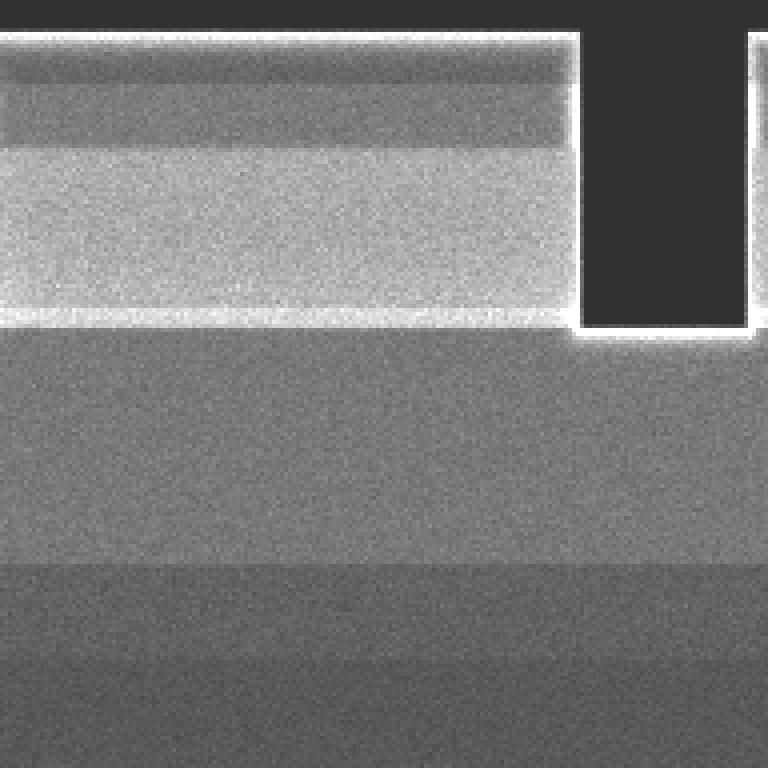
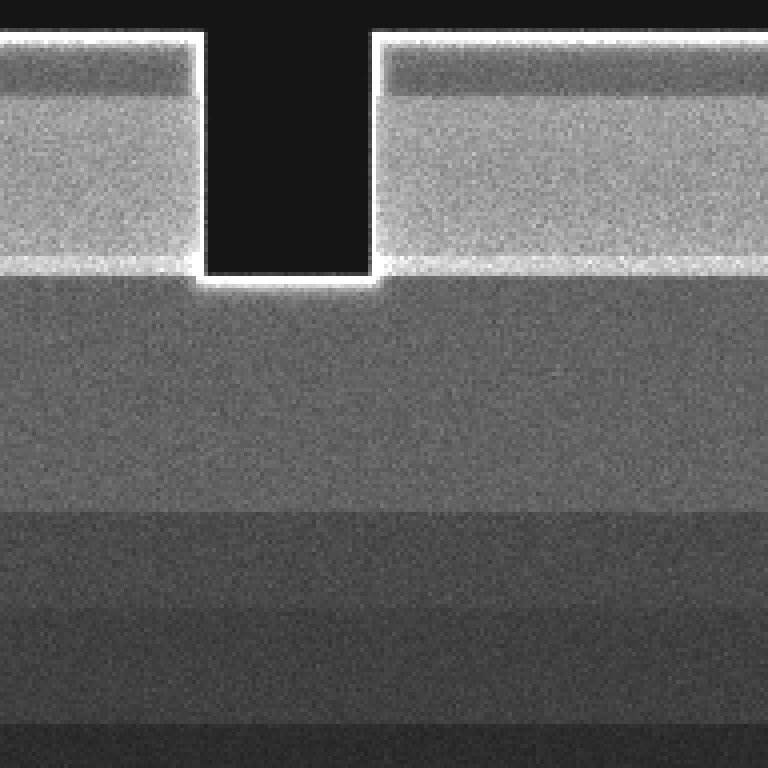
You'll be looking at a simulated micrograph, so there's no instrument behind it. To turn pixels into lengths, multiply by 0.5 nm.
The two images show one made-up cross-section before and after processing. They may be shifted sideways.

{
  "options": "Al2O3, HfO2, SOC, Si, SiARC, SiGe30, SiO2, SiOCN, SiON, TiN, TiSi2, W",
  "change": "removed",
  "material": "SOC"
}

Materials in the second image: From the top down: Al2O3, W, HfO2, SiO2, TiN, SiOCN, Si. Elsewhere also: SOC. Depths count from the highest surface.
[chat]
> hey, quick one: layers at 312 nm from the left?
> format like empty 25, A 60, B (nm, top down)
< Al2O3 32, W 80, HfO2 10, SiO2 118, TiN 48, SiOCN 58, Si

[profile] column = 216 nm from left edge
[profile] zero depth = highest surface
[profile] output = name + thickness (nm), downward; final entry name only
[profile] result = Al2O3 32, W 80, HfO2 10, SiO2 118, TiN 48, SiOCN 58, Si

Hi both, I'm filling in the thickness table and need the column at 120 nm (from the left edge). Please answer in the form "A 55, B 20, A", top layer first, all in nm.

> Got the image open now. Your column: empty 122, SiO2 118, TiN 48, SiOCN 58, Si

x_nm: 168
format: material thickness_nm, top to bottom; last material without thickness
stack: empty 122, SiO2 118, TiN 48, SiOCN 58, Si